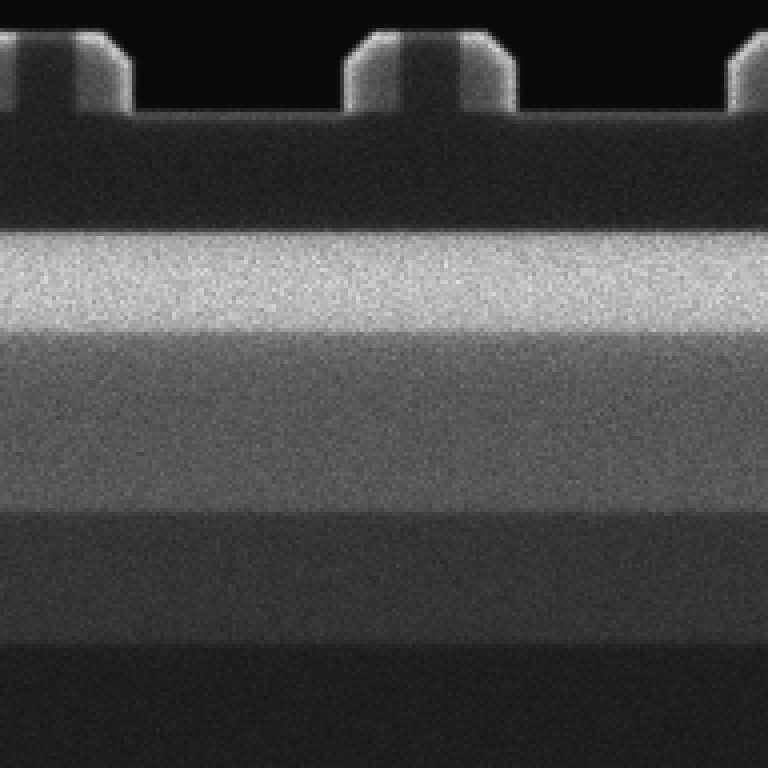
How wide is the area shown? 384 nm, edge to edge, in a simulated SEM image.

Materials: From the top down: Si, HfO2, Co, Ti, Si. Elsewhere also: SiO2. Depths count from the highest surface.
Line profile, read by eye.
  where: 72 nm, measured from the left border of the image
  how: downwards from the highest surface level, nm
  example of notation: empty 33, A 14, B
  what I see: empty 40, Si 60, HfO2 50, Co 90, Ti 66, Si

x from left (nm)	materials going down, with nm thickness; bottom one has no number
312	empty 40, Si 60, HfO2 50, Co 90, Ti 66, Si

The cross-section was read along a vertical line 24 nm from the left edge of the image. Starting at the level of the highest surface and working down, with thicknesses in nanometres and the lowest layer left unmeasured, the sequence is Si 100, HfO2 50, Co 90, Ti 66, Si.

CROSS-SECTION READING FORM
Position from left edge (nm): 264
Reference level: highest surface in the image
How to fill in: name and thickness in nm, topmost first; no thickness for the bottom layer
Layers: empty 40, Si 60, HfO2 50, Co 90, Ti 66, Si